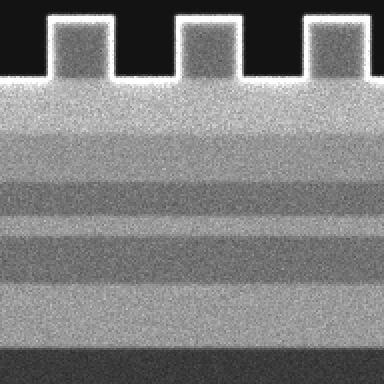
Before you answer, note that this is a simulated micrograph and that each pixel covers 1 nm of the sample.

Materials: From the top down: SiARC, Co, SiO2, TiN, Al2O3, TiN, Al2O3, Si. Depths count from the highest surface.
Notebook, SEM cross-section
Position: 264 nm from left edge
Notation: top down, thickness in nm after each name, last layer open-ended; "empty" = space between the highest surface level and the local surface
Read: empty 62, Co 56, SiO2 48, TiN 34, Al2O3 20, TiN 48, Al2O3 64, Si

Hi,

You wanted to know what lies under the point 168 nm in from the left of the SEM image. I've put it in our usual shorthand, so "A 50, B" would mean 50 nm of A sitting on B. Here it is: empty 62, Co 56, SiO2 48, TiN 34, Al2O3 20, TiN 48, Al2O3 64, Si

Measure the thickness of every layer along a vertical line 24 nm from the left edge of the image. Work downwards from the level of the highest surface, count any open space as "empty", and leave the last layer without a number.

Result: empty 62, Co 56, SiO2 48, TiN 34, Al2O3 20, TiN 48, Al2O3 64, Si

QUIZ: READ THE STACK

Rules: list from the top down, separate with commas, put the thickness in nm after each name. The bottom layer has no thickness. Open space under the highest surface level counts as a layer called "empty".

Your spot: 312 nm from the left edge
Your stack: SiARC 62, Co 56, SiO2 48, TiN 34, Al2O3 20, TiN 48, Al2O3 64, Si